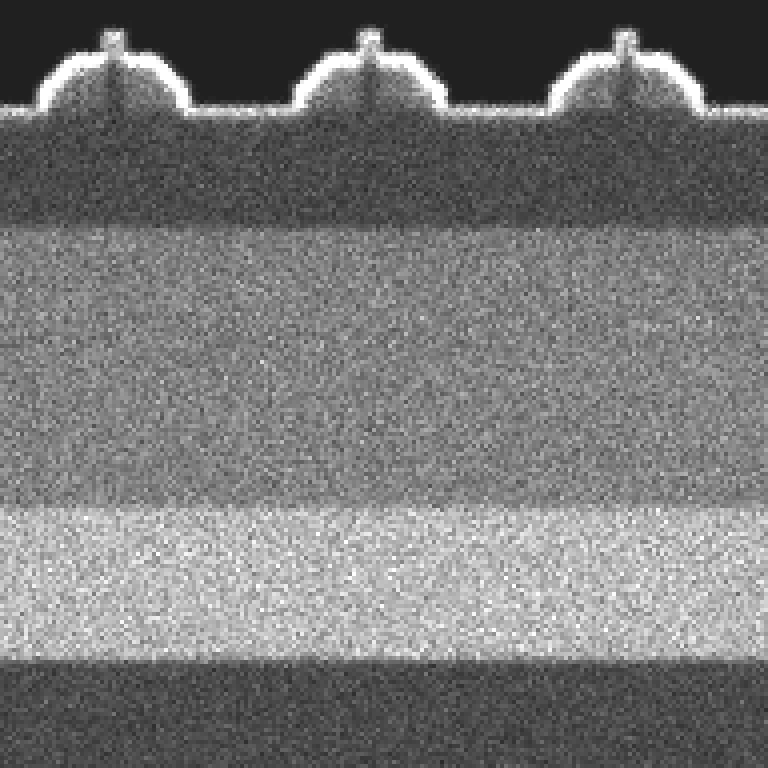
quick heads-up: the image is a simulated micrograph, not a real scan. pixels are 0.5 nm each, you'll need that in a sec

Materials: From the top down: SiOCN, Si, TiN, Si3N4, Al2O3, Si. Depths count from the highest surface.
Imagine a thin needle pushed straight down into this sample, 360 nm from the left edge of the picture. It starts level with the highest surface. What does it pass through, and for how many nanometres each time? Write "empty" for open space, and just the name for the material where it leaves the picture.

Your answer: empty 38, Si 60, TiN 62, Si3N4 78, Al2O3 76, Si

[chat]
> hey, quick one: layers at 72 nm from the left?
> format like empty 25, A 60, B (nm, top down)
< empty 12, SiOCN 26, Si 60, TiN 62, Si3N4 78, Al2O3 76, Si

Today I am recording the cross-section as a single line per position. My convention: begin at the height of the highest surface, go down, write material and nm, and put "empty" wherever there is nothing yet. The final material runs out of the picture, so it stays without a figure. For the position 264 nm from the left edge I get empty 38, Si 60, TiN 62, Si3N4 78, Al2O3 76, Si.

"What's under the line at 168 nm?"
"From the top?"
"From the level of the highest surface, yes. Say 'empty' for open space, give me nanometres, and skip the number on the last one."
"empty 12, SiOCN 26, Si 60, TiN 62, Si3N4 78, Al2O3 76, Si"